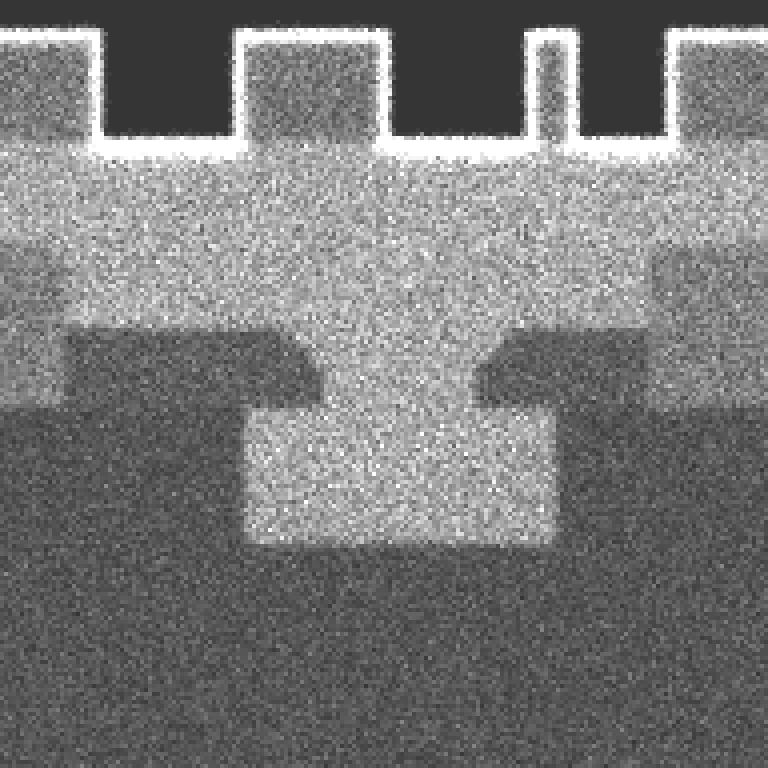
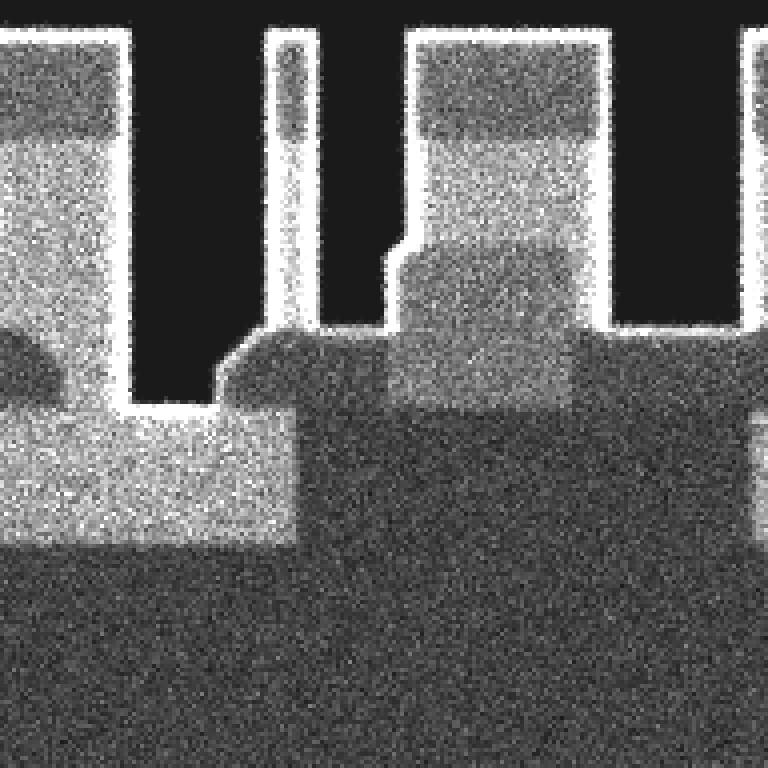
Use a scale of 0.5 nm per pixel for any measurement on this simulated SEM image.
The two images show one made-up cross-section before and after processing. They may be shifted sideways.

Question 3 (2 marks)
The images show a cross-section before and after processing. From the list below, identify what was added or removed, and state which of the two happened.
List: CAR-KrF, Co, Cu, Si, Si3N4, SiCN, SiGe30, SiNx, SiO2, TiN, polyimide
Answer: SiO2 was removed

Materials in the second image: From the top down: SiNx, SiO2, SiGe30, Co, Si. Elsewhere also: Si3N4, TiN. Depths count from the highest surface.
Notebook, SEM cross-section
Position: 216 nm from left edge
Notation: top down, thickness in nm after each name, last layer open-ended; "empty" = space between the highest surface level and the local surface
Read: SiNx 54, SiO2 52, TiN 74, Si3N4 8, Si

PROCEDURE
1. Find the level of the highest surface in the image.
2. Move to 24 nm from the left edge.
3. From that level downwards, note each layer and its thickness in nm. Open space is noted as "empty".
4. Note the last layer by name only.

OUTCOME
SiNx 54, SiO2 108, SiGe30 26, Co 68, Si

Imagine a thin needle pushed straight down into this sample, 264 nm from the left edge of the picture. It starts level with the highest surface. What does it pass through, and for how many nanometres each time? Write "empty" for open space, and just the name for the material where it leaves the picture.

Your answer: SiNx 54, SiO2 52, TiN 74, Si3N4 8, Si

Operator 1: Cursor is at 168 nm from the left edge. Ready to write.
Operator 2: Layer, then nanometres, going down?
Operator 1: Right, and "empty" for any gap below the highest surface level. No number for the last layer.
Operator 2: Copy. empty 148, SiGe30 40, Si